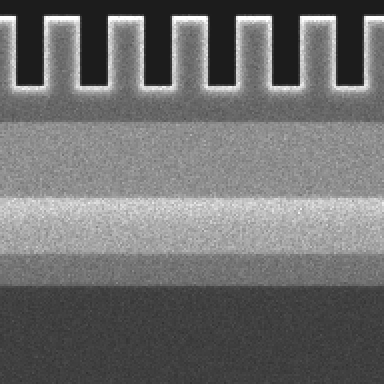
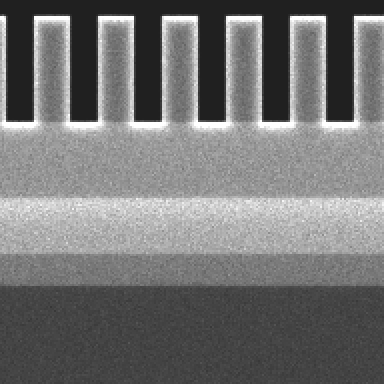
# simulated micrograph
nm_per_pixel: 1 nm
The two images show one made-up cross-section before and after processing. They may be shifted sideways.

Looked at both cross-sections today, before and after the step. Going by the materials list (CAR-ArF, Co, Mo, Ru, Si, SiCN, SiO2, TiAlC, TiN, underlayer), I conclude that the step removed underlayer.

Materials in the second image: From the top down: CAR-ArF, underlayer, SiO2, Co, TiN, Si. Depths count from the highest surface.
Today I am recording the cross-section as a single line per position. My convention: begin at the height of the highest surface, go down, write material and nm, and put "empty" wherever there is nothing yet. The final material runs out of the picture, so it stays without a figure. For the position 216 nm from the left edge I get empty 106, SiO2 76, Co 56, TiN 32, Si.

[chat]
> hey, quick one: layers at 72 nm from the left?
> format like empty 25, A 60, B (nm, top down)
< empty 106, SiO2 76, Co 56, TiN 32, Si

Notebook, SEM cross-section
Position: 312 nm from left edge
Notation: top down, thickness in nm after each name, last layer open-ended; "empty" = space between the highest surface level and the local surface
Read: CAR-ArF 70, underlayer 36, SiO2 76, Co 56, TiN 32, Si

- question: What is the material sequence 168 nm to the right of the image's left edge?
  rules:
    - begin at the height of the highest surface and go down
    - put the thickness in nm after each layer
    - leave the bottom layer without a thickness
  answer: CAR-ArF 70, underlayer 36, SiO2 76, Co 56, TiN 32, Si